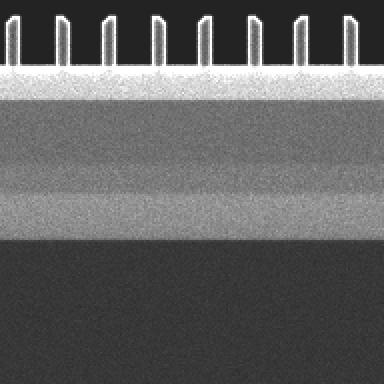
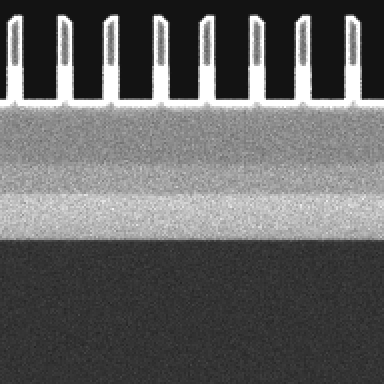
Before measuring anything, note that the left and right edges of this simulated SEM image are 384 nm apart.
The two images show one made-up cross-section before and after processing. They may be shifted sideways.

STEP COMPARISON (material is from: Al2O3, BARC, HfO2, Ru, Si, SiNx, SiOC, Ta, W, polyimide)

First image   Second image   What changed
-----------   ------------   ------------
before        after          HfO2, removed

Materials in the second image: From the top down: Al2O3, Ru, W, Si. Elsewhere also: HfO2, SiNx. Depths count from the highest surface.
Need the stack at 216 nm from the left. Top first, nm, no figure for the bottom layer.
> empty 84, Al2O3 64, Ru 30, W 46, Si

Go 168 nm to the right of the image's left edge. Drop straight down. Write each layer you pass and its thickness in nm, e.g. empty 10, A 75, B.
empty 84, Al2O3 64, Ru 30, W 46, Si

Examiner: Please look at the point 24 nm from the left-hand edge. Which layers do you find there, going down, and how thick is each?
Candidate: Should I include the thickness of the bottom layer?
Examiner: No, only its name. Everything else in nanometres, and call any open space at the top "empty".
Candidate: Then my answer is empty 84, Al2O3 64, Ru 30, W 46, Si